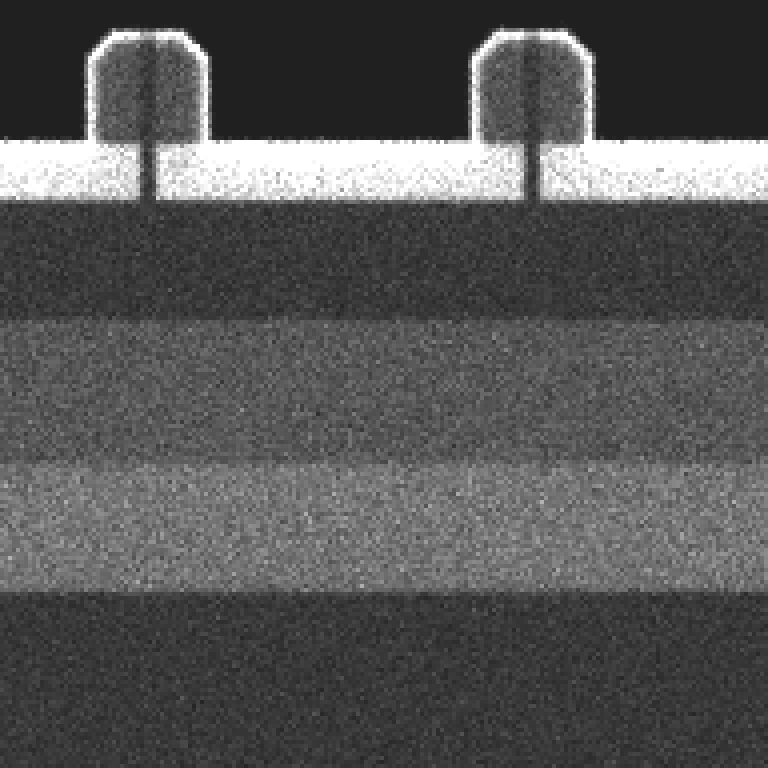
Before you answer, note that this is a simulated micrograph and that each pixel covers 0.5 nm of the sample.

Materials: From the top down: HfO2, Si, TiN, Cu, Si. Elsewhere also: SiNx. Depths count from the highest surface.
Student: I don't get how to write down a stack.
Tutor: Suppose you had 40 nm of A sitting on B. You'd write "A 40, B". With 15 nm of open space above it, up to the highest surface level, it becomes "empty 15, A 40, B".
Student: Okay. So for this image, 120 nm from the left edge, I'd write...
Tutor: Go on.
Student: empty 56, HfO2 28, Si 60, TiN 72, Cu 64, Si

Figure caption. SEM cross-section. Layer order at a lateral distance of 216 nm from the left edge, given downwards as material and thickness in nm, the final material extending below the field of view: empty 56, HfO2 28, Si 60, TiN 72, Cu 64, Si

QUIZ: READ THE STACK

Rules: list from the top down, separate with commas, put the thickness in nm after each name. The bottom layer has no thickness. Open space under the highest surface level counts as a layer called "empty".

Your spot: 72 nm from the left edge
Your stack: Si 144, TiN 72, Cu 64, Si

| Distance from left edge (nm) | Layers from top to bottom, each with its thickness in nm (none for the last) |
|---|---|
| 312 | empty 56, HfO2 28, Si 60, TiN 72, Cu 64, Si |